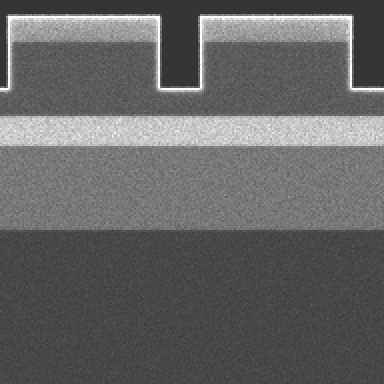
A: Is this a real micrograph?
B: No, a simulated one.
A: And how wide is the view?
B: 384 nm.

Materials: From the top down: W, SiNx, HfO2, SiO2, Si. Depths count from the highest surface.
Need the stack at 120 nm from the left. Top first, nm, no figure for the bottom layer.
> W 26, SiNx 74, HfO2 30, SiO2 84, Si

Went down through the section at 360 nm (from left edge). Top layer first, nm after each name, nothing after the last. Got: empty 72, SiNx 28, HfO2 30, SiO2 84, Si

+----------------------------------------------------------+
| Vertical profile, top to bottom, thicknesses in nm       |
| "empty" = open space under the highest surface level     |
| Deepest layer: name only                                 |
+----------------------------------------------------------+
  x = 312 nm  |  W 26, SiNx 74, HfO2 30, SiO2 84, Si